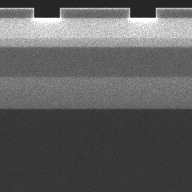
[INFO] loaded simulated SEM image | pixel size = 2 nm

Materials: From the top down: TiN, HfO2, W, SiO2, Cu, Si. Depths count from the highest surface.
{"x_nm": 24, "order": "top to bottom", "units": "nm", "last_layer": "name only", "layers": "TiN 20, HfO2 40, W 18, SiO2 60, Cu 64, Si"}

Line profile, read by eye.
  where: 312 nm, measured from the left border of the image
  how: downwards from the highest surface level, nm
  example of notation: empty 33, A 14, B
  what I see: TiN 20, HfO2 40, W 18, SiO2 60, Cu 64, Si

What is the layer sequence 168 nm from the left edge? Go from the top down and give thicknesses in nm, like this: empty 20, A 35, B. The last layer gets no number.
TiN 20, HfO2 40, W 18, SiO2 60, Cu 64, Si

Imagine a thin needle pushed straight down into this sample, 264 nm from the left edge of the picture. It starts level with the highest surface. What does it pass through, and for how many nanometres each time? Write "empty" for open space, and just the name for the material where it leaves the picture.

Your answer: empty 20, HfO2 40, W 18, SiO2 60, Cu 64, Si